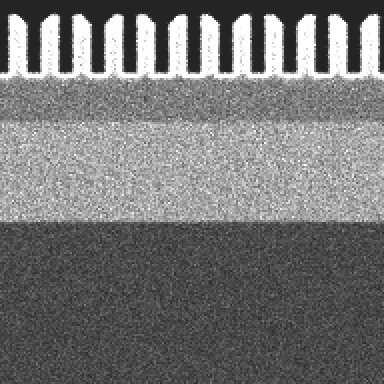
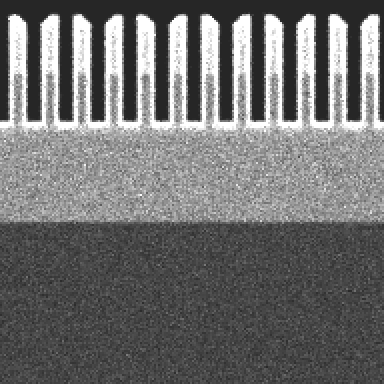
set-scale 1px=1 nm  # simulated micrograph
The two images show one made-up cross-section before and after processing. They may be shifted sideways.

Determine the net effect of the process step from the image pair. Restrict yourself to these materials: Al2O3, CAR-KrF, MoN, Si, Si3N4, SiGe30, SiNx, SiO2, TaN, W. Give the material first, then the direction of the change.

Si3N4: removed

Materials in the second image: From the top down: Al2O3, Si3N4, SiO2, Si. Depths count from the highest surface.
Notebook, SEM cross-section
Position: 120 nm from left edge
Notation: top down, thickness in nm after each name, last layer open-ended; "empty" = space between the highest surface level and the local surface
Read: Al2O3 58, Si3N4 48, SiO2 100, Si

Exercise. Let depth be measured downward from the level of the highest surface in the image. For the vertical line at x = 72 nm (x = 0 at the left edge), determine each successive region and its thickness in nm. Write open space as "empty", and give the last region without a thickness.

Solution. empty 106, SiO2 100, Si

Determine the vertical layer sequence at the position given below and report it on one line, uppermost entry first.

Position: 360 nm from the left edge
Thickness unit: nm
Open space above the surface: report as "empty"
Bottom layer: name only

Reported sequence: empty 106, SiO2 100, Si